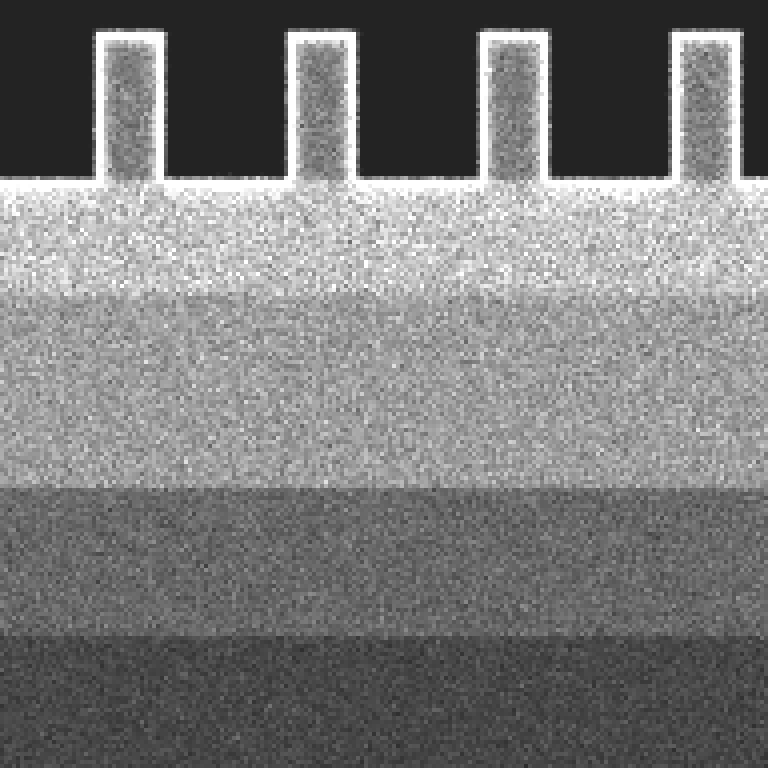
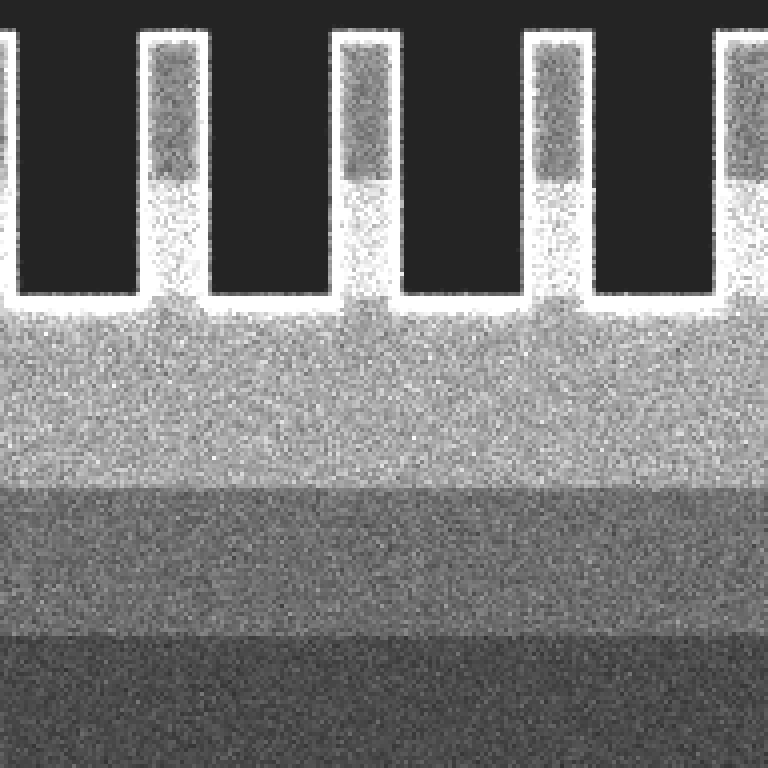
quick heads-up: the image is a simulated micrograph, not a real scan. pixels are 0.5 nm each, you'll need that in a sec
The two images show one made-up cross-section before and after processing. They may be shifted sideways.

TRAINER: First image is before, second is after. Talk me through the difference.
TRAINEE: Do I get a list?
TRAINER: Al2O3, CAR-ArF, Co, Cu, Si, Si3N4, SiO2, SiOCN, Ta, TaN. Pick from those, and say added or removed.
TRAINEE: removed: Co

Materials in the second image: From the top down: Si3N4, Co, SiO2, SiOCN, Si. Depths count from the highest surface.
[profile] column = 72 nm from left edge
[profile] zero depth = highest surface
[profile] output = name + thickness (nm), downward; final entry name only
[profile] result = Si3N4 74, Co 58, SiO2 96, SiOCN 74, Si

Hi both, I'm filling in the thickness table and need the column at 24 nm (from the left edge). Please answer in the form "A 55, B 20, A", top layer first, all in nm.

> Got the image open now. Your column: empty 132, SiO2 96, SiOCN 74, Si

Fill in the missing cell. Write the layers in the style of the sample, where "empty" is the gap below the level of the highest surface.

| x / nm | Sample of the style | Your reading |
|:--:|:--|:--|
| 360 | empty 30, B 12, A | Si3N4 74, Co 58, SiO2 96, SiOCN 74, Si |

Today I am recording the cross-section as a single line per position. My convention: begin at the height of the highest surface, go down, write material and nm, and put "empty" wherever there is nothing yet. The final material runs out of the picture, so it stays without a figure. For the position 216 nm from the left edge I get empty 132, SiO2 96, SiOCN 74, Si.